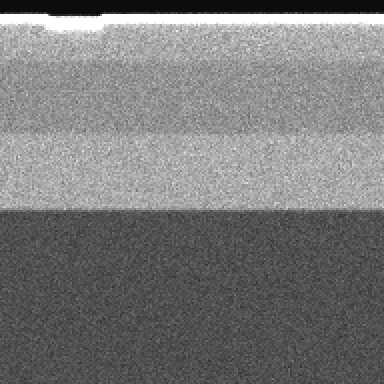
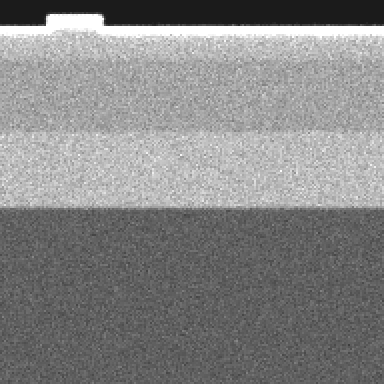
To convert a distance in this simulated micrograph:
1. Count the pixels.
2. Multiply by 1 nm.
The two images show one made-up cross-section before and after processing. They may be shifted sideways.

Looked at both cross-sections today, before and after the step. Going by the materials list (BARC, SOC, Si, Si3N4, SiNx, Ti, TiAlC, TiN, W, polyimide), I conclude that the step removed Si3N4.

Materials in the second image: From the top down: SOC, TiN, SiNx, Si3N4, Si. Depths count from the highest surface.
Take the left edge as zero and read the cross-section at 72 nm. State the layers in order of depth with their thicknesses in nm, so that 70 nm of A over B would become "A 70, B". SOC 12, TiN 32, SiNx 72, Si3N4 76, Si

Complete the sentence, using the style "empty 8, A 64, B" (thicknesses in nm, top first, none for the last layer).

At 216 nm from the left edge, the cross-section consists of empty 12, TiN 32, SiNx 72, Si3N4 76, Si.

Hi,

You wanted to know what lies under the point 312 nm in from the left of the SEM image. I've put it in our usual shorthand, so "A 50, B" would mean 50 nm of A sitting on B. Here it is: empty 12, TiN 32, SiNx 72, Si3N4 76, Si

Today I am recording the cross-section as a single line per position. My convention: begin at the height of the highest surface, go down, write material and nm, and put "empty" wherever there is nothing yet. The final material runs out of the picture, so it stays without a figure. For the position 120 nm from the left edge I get empty 12, TiN 32, SiNx 72, Si3N4 76, Si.